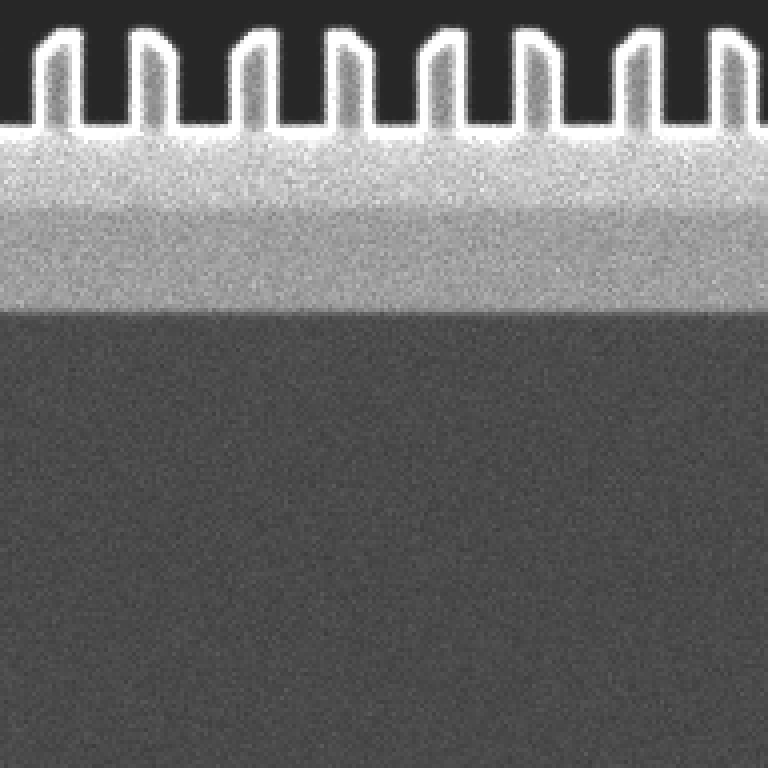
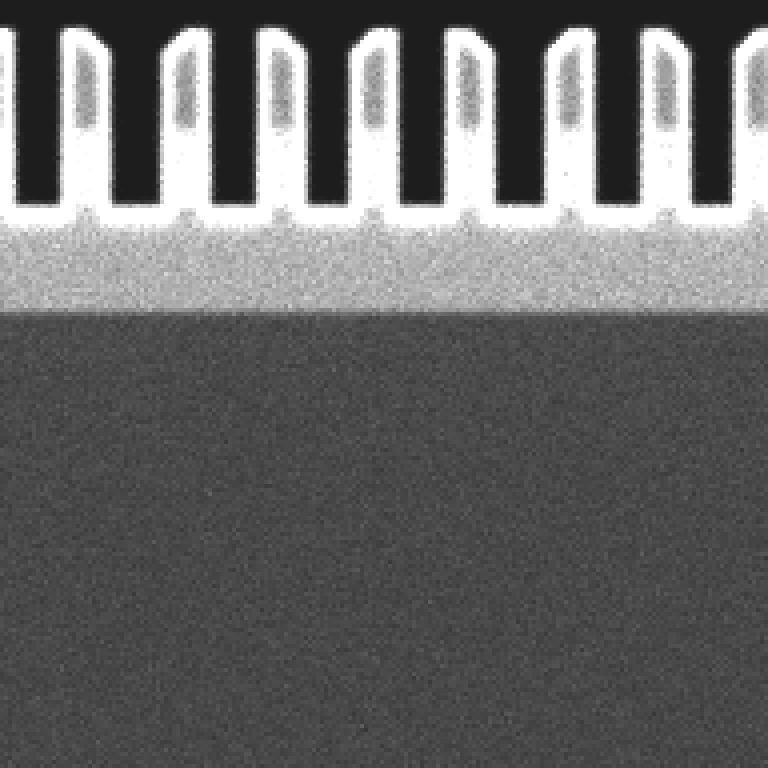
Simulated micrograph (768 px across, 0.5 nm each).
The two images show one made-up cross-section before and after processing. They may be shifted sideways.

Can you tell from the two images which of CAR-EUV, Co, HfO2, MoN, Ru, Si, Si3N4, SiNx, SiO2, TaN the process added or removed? Yes, it removed Co.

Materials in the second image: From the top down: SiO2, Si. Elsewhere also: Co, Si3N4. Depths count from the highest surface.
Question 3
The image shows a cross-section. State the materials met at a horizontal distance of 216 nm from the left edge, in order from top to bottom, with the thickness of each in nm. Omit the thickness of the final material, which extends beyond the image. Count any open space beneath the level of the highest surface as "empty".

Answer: empty 88, SiO2 52, Si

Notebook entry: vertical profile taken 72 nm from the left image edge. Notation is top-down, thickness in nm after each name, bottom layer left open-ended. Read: empty 88, SiO2 52, Si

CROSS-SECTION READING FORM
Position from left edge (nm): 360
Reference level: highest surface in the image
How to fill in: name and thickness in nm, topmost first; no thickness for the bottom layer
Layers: empty 88, SiO2 52, Si